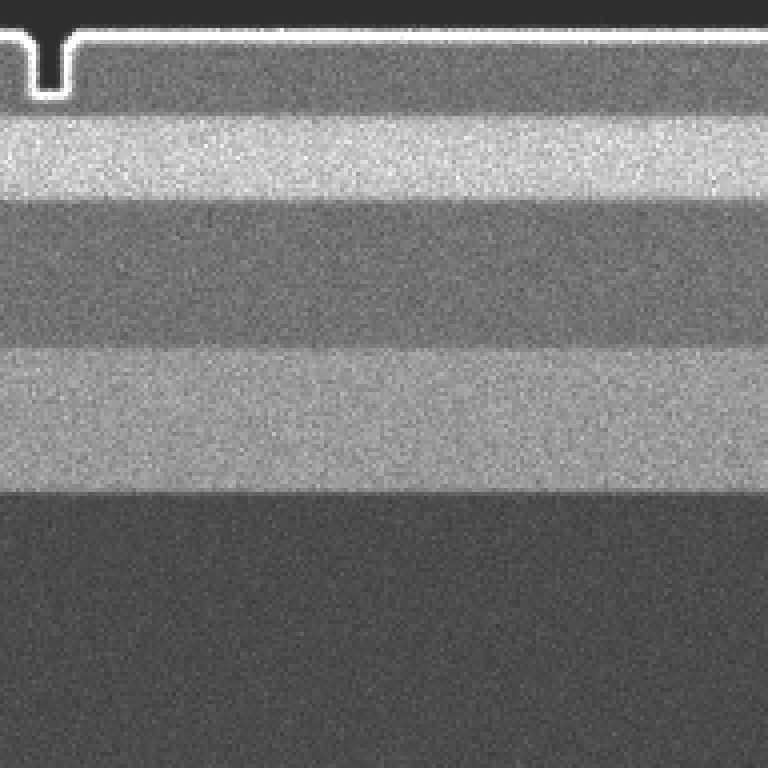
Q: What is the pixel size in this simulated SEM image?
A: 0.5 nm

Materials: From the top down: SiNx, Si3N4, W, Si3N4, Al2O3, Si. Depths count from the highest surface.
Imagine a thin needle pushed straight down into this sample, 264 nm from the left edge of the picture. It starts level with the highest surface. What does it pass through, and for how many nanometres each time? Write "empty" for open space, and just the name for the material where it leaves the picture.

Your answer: SiNx 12, Si3N4 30, W 42, Si3N4 74, Al2O3 72, Si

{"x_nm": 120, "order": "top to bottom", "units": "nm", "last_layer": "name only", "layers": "SiNx 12, Si3N4 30, W 42, Si3N4 74, Al2O3 72, Si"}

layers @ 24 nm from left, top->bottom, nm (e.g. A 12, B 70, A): empty 30, SiNx 12, W 42, Si3N4 74, Al2O3 72, Si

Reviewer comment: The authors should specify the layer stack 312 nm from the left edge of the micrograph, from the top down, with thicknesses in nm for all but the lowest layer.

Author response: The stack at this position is SiNx 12, Si3N4 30, W 42, Si3N4 74, Al2O3 72, Si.